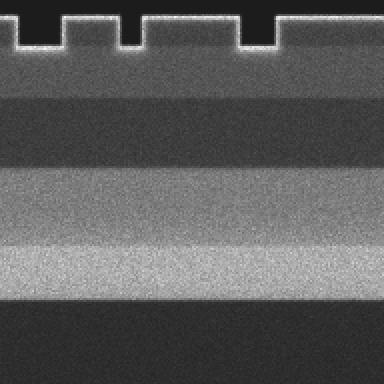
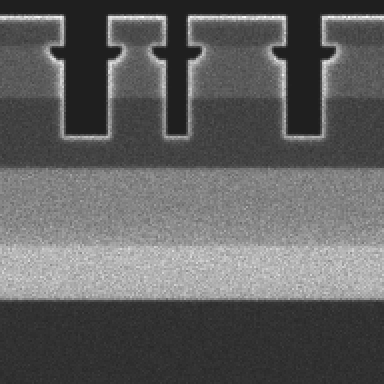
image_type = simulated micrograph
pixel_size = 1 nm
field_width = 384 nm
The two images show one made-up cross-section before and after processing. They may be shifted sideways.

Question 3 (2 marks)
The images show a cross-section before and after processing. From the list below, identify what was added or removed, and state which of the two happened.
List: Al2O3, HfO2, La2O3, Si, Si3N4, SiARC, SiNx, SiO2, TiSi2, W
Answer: SiNx and SiO2 was removed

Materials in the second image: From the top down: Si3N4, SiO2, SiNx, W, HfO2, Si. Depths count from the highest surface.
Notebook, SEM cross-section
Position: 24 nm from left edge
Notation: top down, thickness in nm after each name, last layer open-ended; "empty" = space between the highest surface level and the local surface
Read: Si3N4 30, SiO2 52, SiNx 70, W 78, HfO2 54, Si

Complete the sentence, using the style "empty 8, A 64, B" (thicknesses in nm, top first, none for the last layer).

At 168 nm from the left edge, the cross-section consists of empty 120, SiNx 32, W 78, HfO2 54, Si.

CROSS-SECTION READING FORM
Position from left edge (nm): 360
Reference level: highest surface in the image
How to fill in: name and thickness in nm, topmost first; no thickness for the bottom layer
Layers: Si3N4 30, SiO2 52, SiNx 70, W 78, HfO2 54, Si